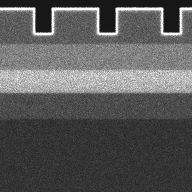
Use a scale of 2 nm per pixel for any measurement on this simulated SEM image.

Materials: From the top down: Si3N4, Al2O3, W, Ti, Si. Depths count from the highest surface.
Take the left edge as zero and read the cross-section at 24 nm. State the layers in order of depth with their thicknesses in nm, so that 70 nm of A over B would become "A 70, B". Si3N4 72, Al2O3 52, W 46, Ti 52, Si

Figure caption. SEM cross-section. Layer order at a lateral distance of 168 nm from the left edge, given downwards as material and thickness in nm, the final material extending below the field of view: Si3N4 72, Al2O3 52, W 46, Ti 52, Si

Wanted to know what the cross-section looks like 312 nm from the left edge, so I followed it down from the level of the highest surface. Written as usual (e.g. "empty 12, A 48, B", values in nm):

Si3N4 72, Al2O3 52, W 46, Ti 52, Si